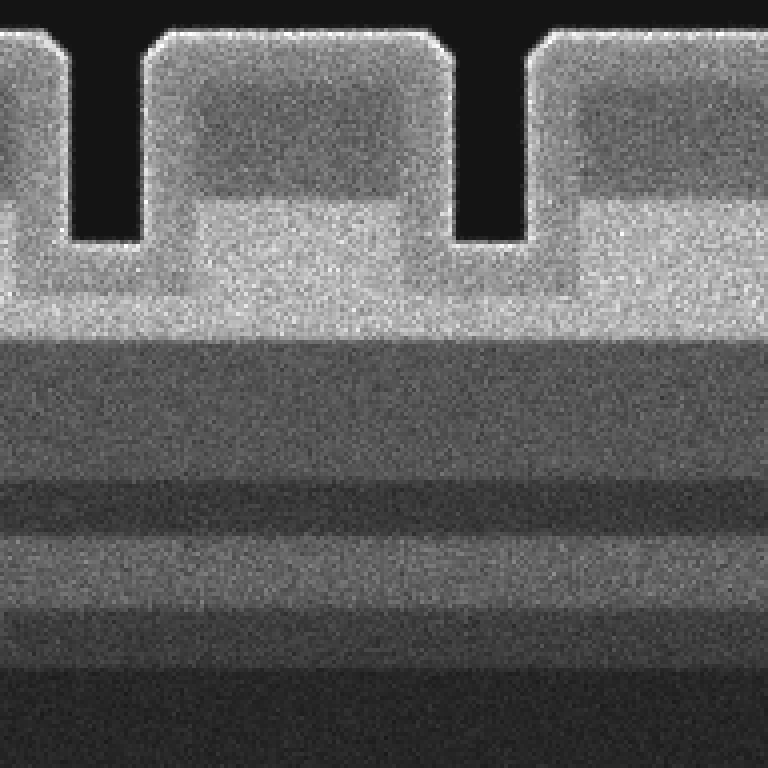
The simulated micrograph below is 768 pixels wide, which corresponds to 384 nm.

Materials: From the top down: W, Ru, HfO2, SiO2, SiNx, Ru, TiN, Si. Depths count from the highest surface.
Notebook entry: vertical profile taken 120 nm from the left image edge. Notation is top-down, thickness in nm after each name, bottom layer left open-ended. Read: W 26, Ru 58, HfO2 70, SiO2 70, SiNx 28, Ru 36, TiN 30, Si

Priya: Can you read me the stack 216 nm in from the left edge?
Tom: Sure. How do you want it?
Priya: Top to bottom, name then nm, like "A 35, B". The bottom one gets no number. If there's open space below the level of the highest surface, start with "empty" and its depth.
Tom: empty 4, W 128, HfO2 22, SiO2 70, SiNx 28, Ru 36, TiN 30, Si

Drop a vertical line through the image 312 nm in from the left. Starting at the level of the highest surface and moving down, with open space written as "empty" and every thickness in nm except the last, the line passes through W 26, Ru 58, HfO2 70, SiO2 70, SiNx 28, Ru 36, TiN 30, Si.